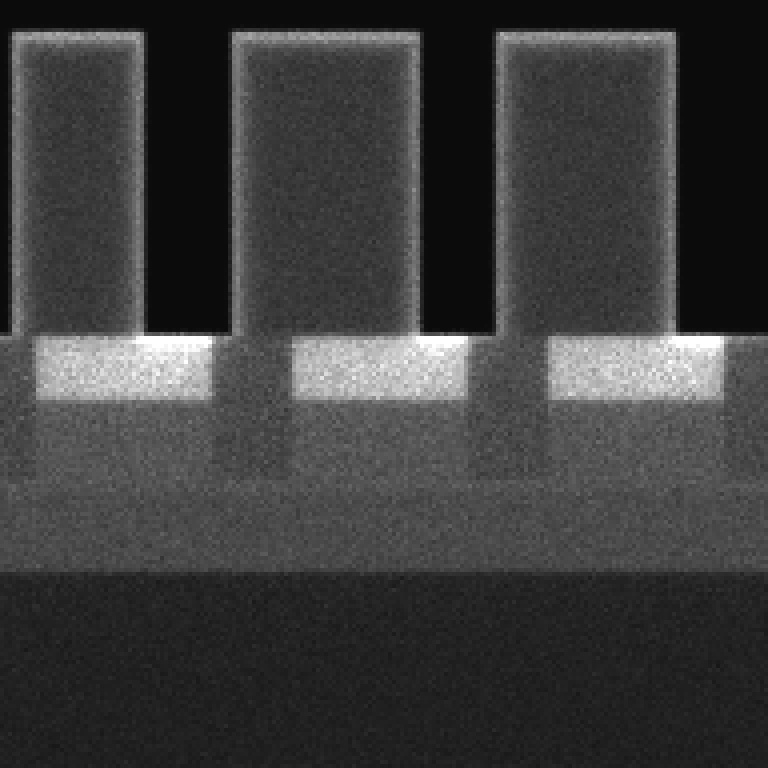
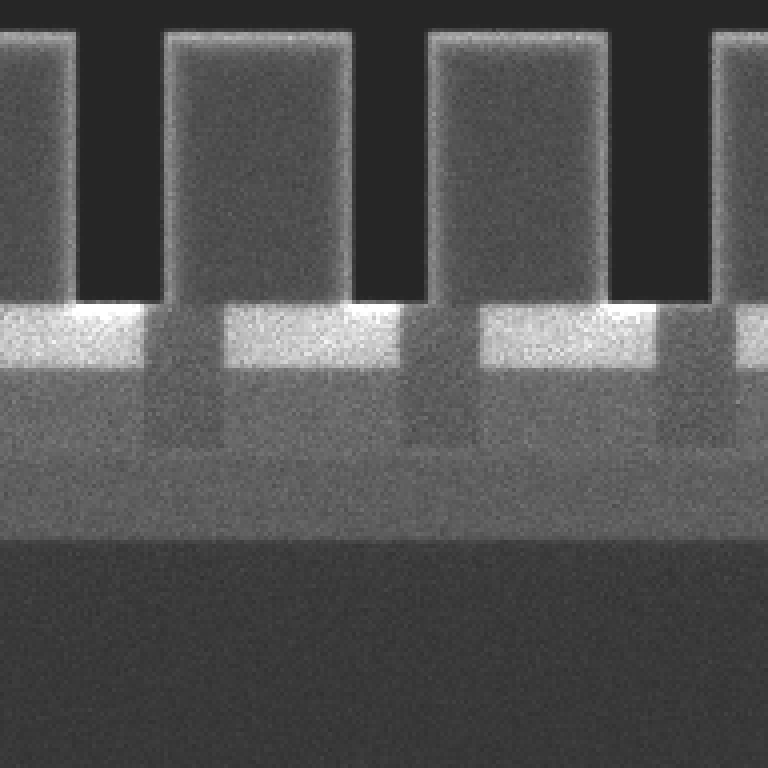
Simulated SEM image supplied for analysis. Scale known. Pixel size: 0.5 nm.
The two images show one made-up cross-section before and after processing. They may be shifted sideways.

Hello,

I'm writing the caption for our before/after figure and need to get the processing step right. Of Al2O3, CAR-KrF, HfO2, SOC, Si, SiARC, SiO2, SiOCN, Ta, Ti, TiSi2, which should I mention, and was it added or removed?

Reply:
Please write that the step removed SiARC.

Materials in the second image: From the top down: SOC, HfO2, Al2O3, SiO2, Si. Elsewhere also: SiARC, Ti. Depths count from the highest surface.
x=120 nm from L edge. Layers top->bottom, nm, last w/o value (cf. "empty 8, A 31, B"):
SOC 136, HfO2 32, Al2O3 46, SiO2 40, Si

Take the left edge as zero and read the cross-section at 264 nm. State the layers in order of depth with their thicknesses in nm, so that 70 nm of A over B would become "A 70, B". SOC 136, HfO2 32, Al2O3 46, SiO2 40, Si